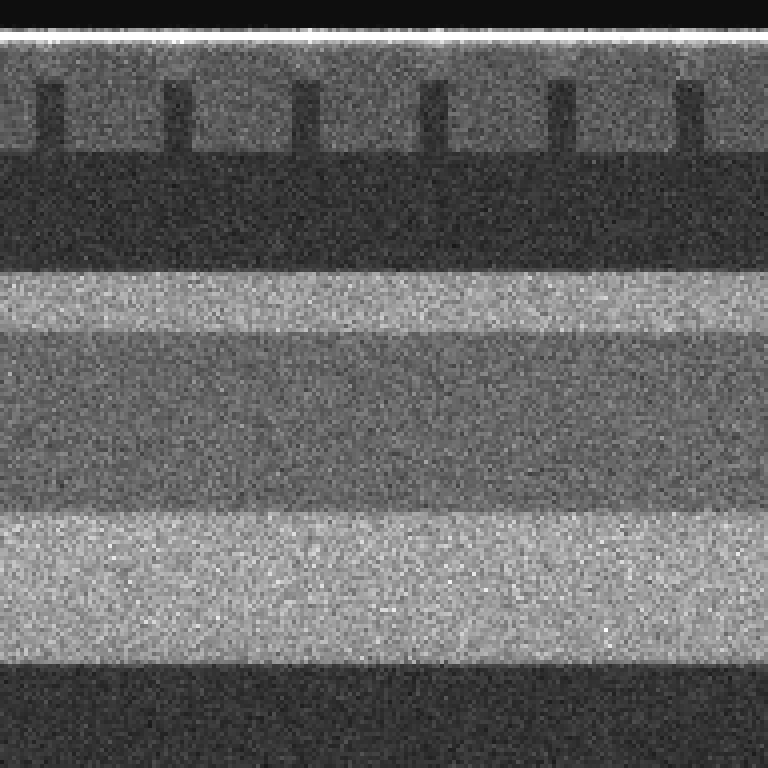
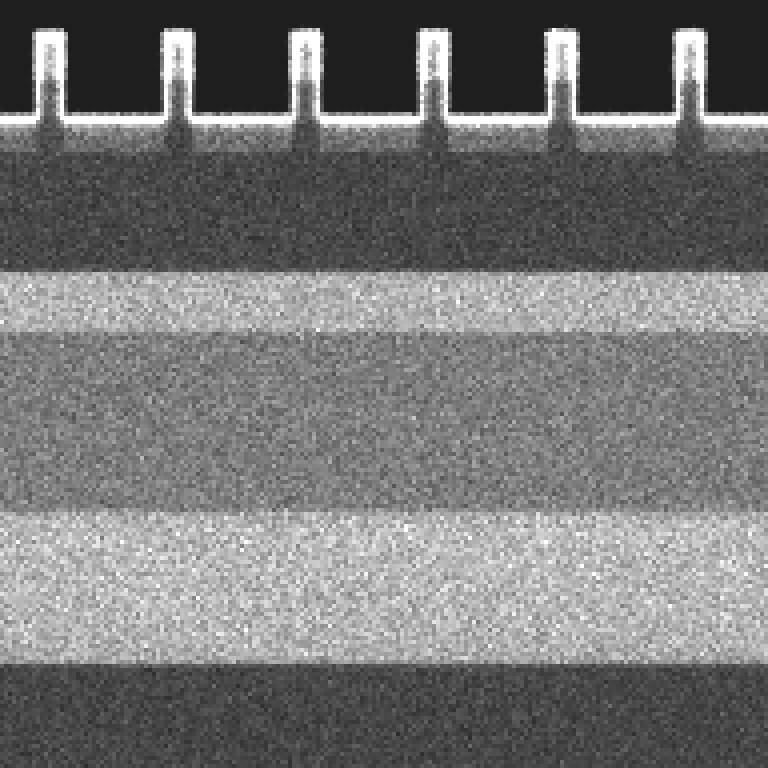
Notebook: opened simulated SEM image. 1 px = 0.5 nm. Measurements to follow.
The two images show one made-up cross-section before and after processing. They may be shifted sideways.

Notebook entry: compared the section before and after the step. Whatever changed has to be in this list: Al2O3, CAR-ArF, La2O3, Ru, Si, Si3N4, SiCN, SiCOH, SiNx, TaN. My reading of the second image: SiNx removed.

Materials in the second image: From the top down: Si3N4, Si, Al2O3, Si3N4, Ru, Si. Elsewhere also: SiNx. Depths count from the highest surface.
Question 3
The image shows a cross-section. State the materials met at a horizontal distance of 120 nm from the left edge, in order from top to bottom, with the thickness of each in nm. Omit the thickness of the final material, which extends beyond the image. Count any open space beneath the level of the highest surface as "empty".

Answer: empty 42, SiNx 18, Si 60, Al2O3 30, Si3N4 90, Ru 76, Si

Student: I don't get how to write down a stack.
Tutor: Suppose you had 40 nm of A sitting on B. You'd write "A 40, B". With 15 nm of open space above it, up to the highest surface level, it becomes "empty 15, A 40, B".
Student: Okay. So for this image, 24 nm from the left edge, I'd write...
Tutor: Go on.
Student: Si3N4 24, Si 96, Al2O3 30, Si3N4 90, Ru 76, Si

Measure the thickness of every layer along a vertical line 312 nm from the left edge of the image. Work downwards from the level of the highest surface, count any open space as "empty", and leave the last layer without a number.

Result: empty 42, SiNx 18, Si 60, Al2O3 30, Si3N4 90, Ru 76, Si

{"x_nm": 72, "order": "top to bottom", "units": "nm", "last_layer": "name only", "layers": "empty 42, SiNx 18, Si 60, Al2O3 30, Si3N4 90, Ru 76, Si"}